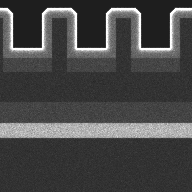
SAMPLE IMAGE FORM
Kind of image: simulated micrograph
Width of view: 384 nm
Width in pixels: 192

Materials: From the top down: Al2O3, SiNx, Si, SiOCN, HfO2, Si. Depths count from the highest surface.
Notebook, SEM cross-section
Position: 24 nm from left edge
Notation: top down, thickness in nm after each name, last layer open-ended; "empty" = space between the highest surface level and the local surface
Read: empty 10, Al2O3 90, SiNx 28, Si 60, SiOCN 42, HfO2 30, Si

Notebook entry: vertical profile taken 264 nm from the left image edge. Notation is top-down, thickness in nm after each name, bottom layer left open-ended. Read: Al2O3 100, SiNx 28, Si 60, SiOCN 42, HfO2 30, Si